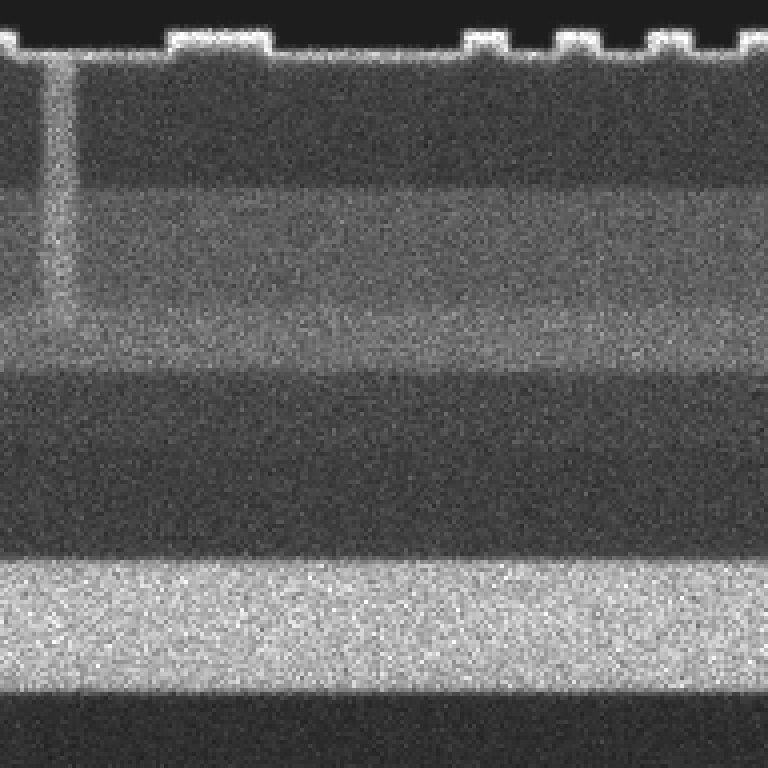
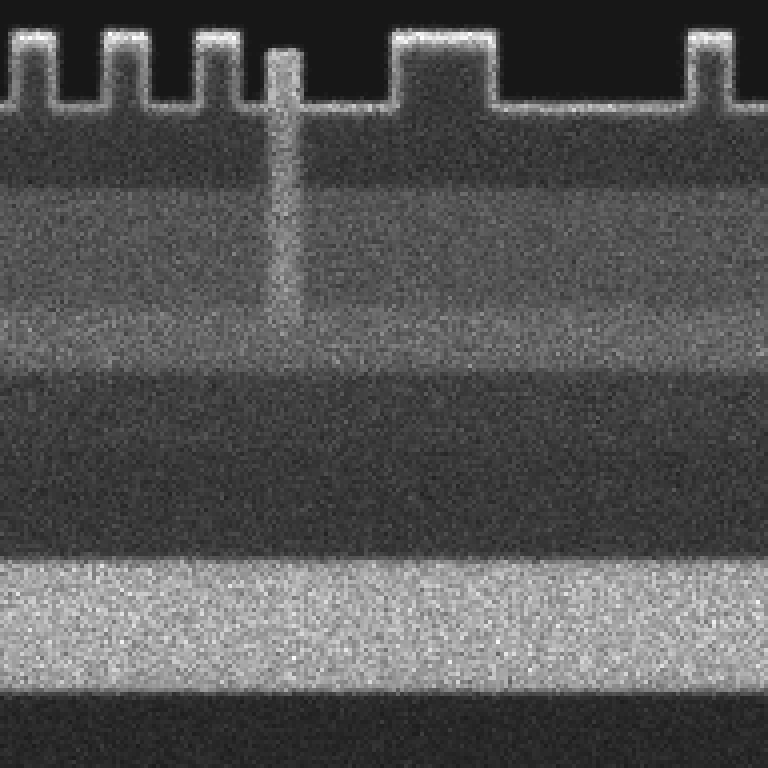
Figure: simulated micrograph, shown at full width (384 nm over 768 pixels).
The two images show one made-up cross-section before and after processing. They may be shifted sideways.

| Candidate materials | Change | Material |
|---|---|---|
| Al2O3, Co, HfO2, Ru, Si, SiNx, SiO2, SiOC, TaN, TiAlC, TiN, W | removed | SiNx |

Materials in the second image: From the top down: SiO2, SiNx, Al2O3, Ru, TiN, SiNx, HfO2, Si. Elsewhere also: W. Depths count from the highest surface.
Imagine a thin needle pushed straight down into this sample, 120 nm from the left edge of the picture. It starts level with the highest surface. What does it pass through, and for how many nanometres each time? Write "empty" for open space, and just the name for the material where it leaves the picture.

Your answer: empty 36, SiNx 42, Al2O3 60, Ru 32, TiN 38, SiNx 56, HfO2 66, Si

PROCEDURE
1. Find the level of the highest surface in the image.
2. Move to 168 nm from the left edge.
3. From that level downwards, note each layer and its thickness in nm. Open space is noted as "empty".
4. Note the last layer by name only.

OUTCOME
empty 36, SiNx 42, Al2O3 60, Ru 32, TiN 38, SiNx 56, HfO2 66, Si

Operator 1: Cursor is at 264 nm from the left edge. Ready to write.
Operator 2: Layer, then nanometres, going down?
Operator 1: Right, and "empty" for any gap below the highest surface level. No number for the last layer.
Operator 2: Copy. empty 36, SiNx 42, Al2O3 60, Ru 32, TiN 38, SiNx 56, HfO2 66, Si